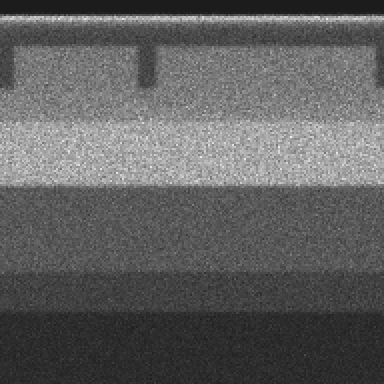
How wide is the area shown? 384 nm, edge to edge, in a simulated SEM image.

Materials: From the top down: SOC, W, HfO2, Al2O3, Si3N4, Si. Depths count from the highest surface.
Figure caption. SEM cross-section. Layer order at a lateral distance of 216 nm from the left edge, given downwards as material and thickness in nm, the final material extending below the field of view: SOC 30, W 76, HfO2 64, Al2O3 86, Si3N4 40, Si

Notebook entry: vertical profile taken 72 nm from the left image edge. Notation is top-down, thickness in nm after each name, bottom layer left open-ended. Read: SOC 30, W 76, HfO2 64, Al2O3 86, Si3N4 40, Si